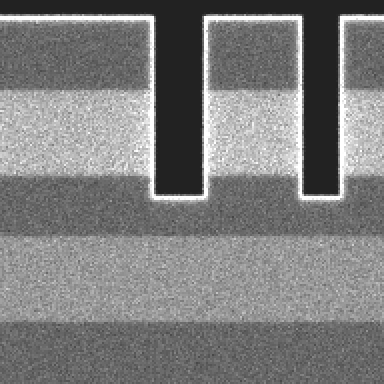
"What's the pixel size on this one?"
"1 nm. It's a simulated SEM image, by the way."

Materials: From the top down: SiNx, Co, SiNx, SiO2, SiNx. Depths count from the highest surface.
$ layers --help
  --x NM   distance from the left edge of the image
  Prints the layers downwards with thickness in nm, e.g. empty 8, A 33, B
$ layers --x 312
empty 180, SiNx 40, SiO2 86, SiNx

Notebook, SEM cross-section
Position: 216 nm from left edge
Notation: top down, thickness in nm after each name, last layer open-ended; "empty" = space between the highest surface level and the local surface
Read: SiNx 74, Co 86, SiNx 60, SiO2 86, SiNx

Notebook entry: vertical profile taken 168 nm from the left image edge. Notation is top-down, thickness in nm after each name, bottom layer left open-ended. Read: empty 180, SiNx 40, SiO2 86, SiNx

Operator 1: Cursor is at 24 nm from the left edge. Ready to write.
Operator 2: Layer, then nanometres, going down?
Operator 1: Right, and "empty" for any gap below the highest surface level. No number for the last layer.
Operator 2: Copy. SiNx 74, Co 86, SiNx 60, SiO2 86, SiNx